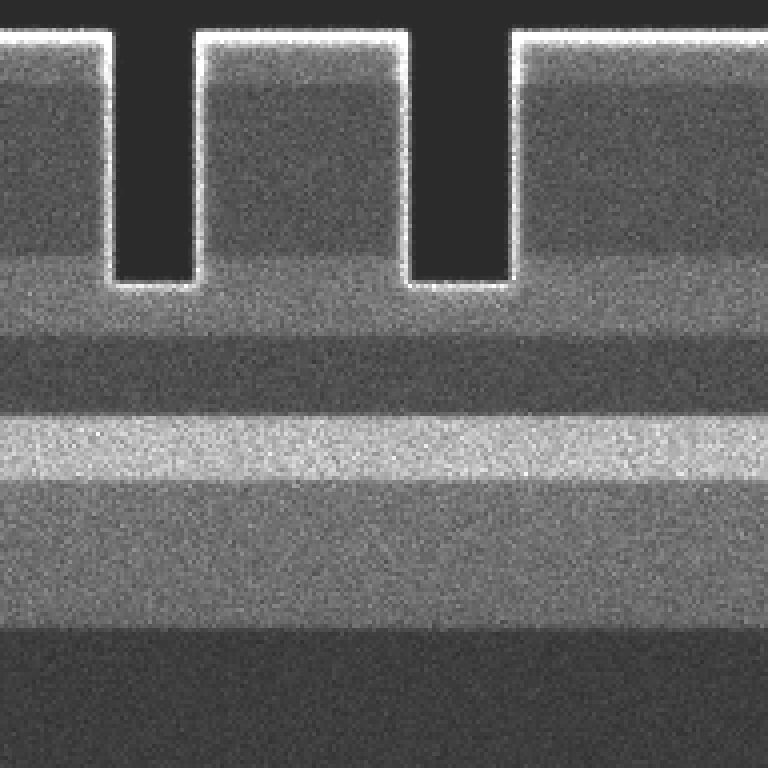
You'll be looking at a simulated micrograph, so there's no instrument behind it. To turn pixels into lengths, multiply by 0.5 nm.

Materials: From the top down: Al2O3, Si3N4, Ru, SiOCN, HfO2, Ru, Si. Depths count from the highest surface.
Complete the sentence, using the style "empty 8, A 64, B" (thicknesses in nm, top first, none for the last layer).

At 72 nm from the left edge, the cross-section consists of empty 126, Ru 26, SiOCN 40, HfO2 32, Ru 74, Si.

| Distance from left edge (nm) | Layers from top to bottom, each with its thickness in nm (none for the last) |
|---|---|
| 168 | Al2O3 26, Si3N4 86, Ru 40, SiOCN 40, HfO2 32, Ru 74, Si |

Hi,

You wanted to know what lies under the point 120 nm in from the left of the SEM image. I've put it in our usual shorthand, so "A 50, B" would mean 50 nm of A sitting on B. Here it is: Al2O3 26, Si3N4 86, Ru 40, SiOCN 40, HfO2 32, Ru 74, Si